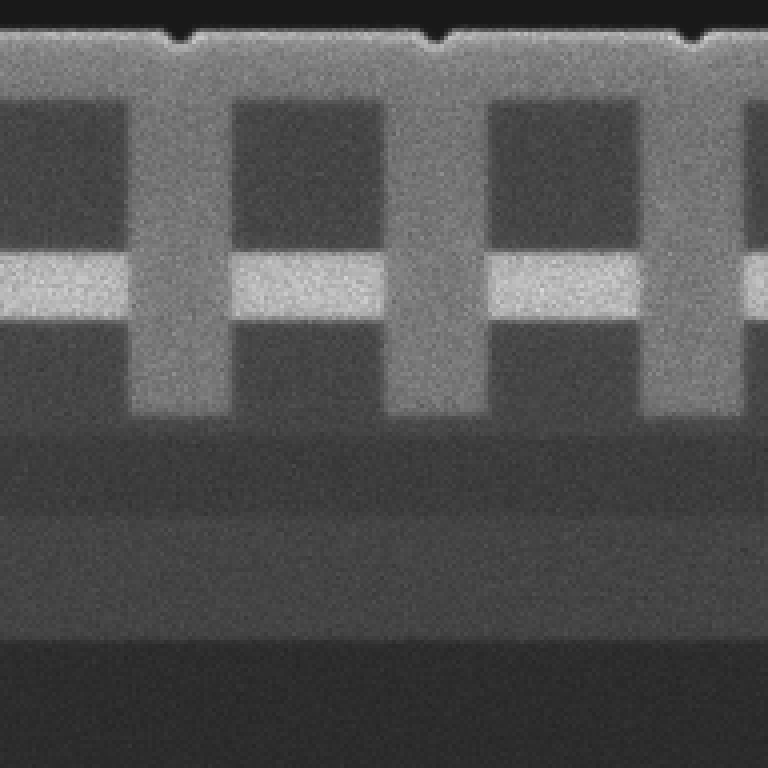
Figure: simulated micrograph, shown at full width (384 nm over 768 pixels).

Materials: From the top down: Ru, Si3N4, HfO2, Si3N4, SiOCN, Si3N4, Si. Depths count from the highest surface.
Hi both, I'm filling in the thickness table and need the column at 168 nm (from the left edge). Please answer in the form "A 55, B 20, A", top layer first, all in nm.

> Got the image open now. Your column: Ru 34, Si3N4 76, HfO2 34, Si3N4 58, SiOCN 40, Si3N4 62, Si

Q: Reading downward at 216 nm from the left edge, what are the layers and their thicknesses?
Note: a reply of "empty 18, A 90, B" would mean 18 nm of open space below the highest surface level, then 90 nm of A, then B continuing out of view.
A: empty 6, Ru 186, Si3N4 10, SiOCN 40, Si3N4 62, Si